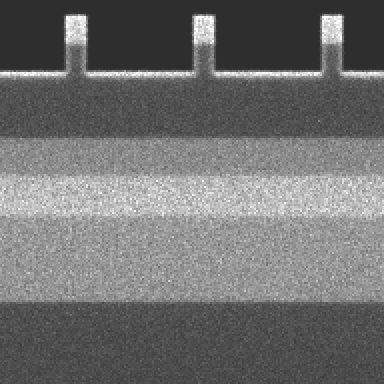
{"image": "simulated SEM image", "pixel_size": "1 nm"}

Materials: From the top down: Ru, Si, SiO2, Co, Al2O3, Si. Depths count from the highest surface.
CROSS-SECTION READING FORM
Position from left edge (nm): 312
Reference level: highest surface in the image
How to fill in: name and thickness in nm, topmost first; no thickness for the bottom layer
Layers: empty 56, Si 66, SiO2 38, Co 40, Al2O3 86, Si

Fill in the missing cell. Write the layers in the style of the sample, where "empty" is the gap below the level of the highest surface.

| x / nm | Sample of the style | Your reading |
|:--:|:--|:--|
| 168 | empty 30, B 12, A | empty 56, Si 66, SiO2 38, Co 40, Al2O3 86, Si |